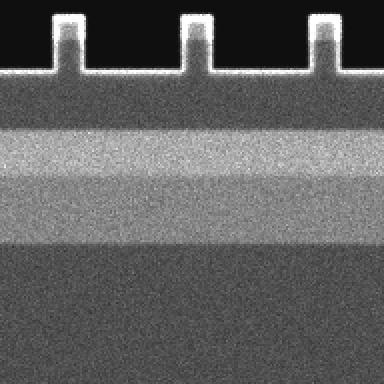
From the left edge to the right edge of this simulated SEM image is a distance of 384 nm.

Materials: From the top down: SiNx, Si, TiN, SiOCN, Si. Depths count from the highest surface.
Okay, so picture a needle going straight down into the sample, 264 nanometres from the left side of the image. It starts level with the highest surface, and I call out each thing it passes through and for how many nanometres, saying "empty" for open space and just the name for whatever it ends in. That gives empty 54, Si 60, TiN 46, SiOCN 68, Si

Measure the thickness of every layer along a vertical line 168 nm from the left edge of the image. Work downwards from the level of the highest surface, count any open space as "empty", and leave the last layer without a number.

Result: empty 54, Si 60, TiN 46, SiOCN 68, Si